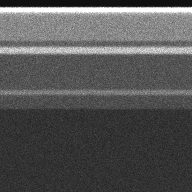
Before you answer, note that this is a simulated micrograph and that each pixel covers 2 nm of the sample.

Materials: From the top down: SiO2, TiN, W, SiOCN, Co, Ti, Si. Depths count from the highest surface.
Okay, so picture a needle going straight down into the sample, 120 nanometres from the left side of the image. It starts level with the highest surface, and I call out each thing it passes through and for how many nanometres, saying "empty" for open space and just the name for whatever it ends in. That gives SiO2 66, TiN 12, W 14, SiOCN 72, Co 10, Ti 28, Si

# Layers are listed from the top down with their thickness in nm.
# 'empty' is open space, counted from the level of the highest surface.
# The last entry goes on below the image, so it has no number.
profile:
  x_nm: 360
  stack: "SiO2 66, TiN 12, W 14, SiOCN 72, Co 10, Ti 28, Si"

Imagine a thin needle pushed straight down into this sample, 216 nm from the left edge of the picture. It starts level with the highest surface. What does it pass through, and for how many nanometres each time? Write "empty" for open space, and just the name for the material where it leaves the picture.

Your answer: SiO2 66, TiN 12, W 14, SiOCN 72, Co 10, Ti 28, Si